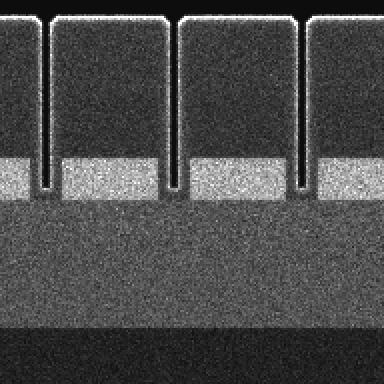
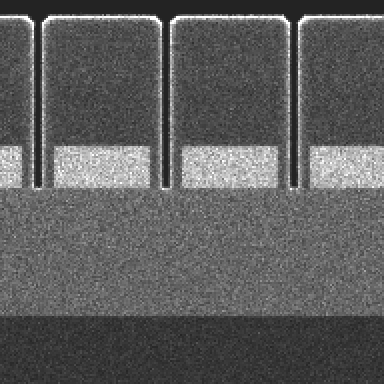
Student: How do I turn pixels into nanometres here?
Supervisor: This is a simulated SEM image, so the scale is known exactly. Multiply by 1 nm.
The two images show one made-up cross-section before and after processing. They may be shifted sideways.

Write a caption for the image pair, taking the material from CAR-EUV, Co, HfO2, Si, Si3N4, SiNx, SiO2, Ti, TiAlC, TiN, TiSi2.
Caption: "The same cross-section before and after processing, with Si3N4 removed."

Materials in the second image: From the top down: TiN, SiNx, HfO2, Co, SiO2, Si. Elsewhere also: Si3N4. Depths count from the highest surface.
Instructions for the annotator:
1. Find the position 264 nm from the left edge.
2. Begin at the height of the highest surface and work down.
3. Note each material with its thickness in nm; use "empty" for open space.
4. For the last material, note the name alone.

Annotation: TiN 68, SiNx 62, HfO2 42, Co 68, SiO2 60, Si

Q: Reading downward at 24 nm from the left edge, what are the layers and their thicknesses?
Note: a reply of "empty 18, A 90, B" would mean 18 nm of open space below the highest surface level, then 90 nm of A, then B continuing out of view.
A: Si3N4 172, Co 68, SiO2 60, Si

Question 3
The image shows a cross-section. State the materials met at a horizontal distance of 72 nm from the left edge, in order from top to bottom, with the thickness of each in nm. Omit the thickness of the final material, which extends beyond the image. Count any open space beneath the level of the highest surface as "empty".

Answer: TiN 68, SiNx 62, HfO2 42, Co 68, SiO2 60, Si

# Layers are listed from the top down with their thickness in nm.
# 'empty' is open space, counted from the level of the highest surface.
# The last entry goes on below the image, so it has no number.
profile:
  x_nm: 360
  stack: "TiN 68, SiNx 62, HfO2 42, Co 68, SiO2 60, Si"